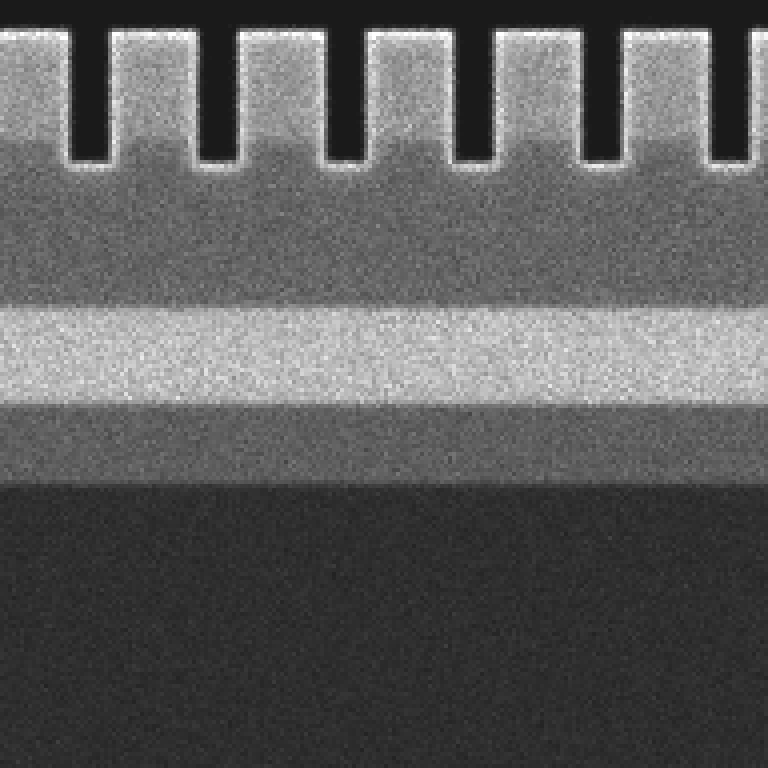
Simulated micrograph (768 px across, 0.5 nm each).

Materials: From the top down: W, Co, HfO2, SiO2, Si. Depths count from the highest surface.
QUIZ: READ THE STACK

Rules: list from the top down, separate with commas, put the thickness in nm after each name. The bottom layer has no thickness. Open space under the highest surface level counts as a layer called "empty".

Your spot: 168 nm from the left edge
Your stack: empty 66, Co 72, HfO2 48, SiO2 40, Si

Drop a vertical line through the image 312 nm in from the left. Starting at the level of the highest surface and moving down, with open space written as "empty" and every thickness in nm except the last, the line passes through W 54, Co 84, HfO2 48, SiO2 40, Si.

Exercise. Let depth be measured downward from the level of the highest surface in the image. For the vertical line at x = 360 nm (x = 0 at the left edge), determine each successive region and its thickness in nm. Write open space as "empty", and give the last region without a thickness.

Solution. empty 66, Co 72, HfO2 48, SiO2 40, Si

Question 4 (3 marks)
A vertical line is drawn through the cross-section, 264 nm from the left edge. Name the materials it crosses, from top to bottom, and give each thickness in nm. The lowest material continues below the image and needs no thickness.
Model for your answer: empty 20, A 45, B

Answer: W 54, Co 84, HfO2 48, SiO2 40, Si